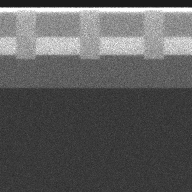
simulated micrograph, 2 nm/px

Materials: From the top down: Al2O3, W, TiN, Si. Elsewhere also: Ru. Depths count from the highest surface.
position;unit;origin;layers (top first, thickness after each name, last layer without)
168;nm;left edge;Ru 102, TiN 58, Si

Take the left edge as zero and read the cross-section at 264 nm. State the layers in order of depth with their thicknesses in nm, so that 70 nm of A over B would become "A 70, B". Al2O3 58, W 36, TiN 66, Si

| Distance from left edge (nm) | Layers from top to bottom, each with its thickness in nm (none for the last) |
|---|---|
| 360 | Al2O3 58, W 36, TiN 66, Si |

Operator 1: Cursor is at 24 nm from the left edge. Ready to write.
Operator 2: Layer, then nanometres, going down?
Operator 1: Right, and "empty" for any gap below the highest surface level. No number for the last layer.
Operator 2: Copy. Al2O3 58, W 36, TiN 66, Si